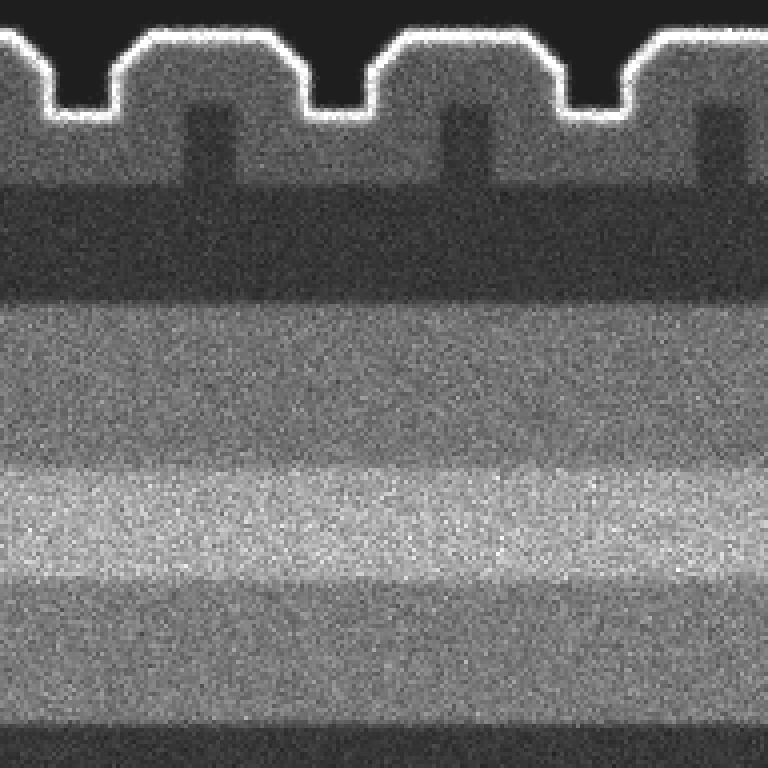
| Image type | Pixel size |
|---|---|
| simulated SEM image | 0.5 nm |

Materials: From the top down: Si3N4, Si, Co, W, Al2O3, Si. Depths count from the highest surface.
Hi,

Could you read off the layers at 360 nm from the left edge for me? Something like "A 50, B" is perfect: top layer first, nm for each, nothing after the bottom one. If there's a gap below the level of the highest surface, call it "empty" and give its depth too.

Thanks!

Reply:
Si3N4 36, Si 100, Co 82, W 56, Al2O3 72, Si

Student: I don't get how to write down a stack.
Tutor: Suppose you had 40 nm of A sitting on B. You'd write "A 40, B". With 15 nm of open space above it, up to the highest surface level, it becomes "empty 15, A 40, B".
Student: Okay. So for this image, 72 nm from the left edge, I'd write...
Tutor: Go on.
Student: empty 2, Si3N4 74, Si 60, Co 82, W 56, Al2O3 72, Si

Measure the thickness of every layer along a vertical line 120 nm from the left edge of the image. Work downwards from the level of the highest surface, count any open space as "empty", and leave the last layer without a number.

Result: Si3N4 76, Si 60, Co 82, W 56, Al2O3 72, Si